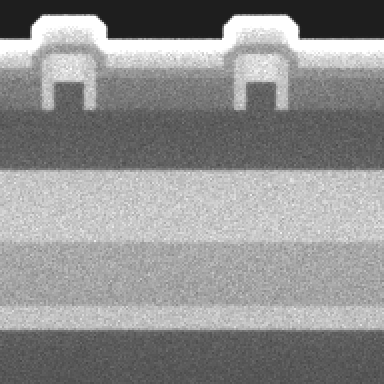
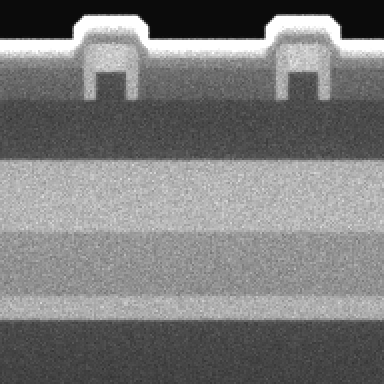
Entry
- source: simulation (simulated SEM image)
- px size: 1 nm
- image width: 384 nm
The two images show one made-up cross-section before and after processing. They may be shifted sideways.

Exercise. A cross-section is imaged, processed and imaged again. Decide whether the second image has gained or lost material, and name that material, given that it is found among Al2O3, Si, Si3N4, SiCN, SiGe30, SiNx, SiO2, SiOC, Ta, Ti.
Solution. removed: SiO2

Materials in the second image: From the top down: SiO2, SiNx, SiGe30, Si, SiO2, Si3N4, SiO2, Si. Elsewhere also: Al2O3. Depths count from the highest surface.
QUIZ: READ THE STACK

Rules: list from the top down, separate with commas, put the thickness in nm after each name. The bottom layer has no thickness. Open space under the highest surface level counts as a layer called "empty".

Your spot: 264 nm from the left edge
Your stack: empty 24, SiO2 18, SiNx 10, SiGe30 32, Si 60, SiO2 72, Si3N4 64, SiO2 24, Si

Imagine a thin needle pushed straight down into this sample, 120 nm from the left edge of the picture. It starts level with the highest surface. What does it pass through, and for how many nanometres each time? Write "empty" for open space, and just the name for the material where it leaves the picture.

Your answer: SiO2 18, SiNx 10, Al2O3 28, Si 88, SiO2 72, Si3N4 64, SiO2 24, Si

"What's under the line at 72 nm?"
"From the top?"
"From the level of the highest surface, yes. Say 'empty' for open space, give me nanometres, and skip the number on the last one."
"empty 24, SiO2 18, SiNx 10, SiGe30 32, Si 60, SiO2 72, Si3N4 64, SiO2 24, Si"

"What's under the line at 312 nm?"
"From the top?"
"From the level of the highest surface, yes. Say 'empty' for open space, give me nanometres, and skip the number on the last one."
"SiO2 18, SiNx 10, Al2O3 28, Si 88, SiO2 72, Si3N4 64, SiO2 24, Si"